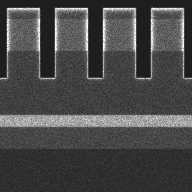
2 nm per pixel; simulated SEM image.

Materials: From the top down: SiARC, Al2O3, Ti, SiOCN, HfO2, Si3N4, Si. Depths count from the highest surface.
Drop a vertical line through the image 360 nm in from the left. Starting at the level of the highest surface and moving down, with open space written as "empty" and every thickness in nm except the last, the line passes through SiARC 22, Al2O3 64, Ti 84, SiOCN 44, HfO2 24, Si3N4 44, Si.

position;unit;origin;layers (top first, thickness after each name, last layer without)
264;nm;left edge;SiARC 22, Al2O3 64, Ti 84, SiOCN 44, HfO2 24, Si3N4 44, Si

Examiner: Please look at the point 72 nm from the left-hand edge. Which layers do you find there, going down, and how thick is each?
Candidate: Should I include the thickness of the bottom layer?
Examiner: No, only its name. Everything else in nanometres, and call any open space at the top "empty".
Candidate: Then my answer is SiARC 22, Al2O3 64, Ti 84, SiOCN 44, HfO2 24, Si3N4 44, Si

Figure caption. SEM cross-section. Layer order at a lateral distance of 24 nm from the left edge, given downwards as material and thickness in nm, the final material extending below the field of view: SiARC 22, Al2O3 64, Ti 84, SiOCN 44, HfO2 24, Si3N4 44, Si